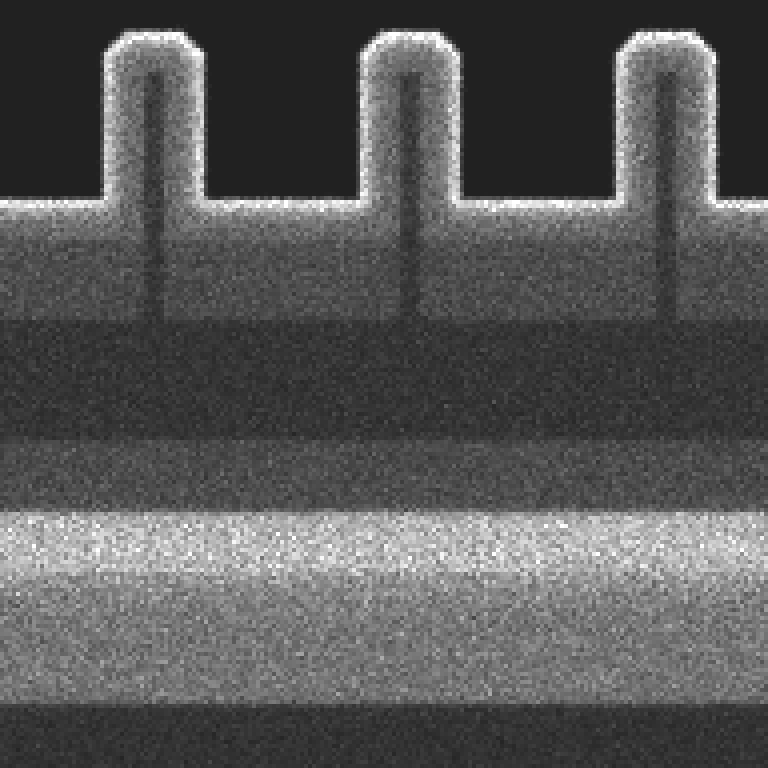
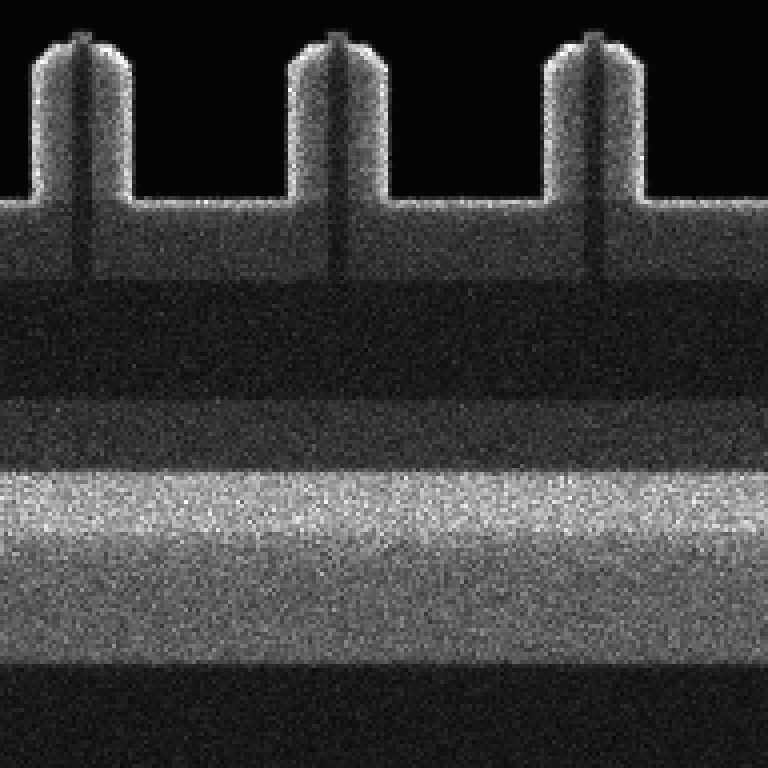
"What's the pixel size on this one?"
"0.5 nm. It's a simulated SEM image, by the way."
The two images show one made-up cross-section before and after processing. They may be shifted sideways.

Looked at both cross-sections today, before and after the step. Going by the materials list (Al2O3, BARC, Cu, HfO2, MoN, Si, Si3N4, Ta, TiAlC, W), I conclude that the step removed Al2O3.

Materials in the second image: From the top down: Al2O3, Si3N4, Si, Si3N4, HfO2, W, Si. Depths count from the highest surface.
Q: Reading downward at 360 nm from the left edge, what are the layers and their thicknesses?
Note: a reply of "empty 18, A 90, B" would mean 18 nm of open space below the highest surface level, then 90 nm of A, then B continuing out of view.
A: empty 84, Si3N4 40, Si 60, Si3N4 36, HfO2 30, W 66, Si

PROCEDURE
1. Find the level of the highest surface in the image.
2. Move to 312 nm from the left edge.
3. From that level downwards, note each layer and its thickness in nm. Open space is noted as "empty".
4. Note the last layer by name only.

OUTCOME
empty 8, Al2O3 76, Si3N4 40, Si 60, Si3N4 36, HfO2 30, W 66, Si